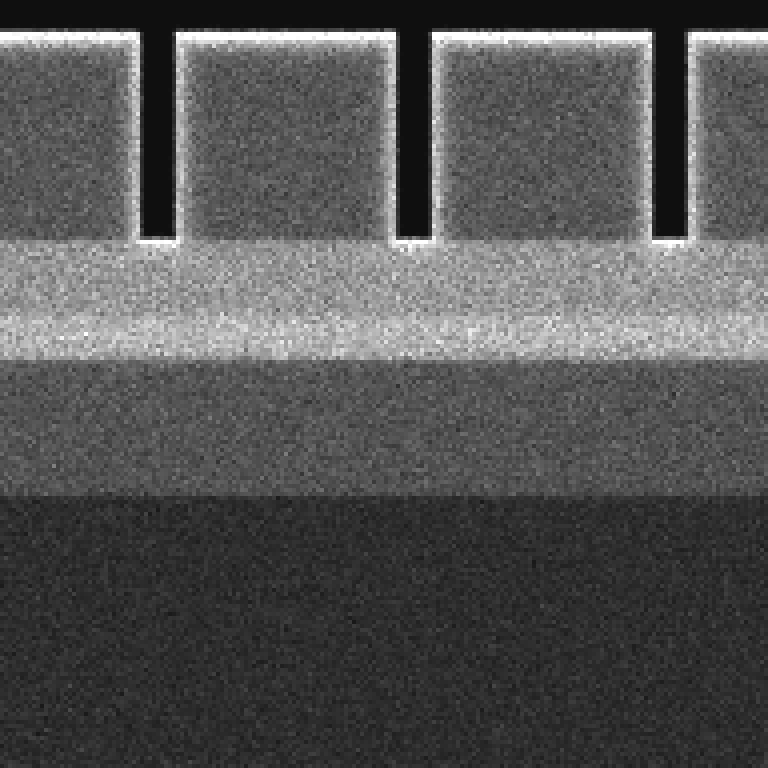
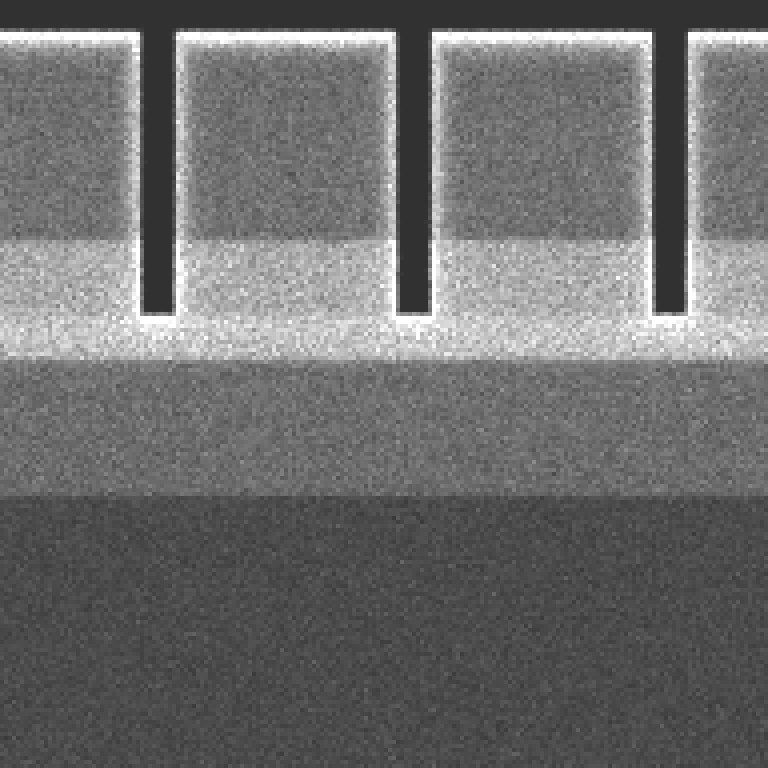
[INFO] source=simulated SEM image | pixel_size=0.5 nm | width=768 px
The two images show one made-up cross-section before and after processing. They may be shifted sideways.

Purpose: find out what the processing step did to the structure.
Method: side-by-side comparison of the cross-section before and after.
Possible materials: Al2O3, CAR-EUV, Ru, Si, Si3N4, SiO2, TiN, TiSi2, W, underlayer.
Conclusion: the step removed Ru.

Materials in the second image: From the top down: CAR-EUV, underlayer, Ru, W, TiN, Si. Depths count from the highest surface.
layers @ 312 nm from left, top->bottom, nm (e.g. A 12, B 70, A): CAR-EUV 44, underlayer 60, Ru 38, W 22, TiN 68, Si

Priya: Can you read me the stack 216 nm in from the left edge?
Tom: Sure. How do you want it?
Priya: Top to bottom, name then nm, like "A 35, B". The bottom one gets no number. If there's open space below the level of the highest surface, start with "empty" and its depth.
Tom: CAR-EUV 44, underlayer 60, Ru 38, W 22, TiN 68, Si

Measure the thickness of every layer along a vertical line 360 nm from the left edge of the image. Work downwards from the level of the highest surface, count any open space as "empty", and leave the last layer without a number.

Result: CAR-EUV 44, underlayer 60, Ru 38, W 22, TiN 68, Si